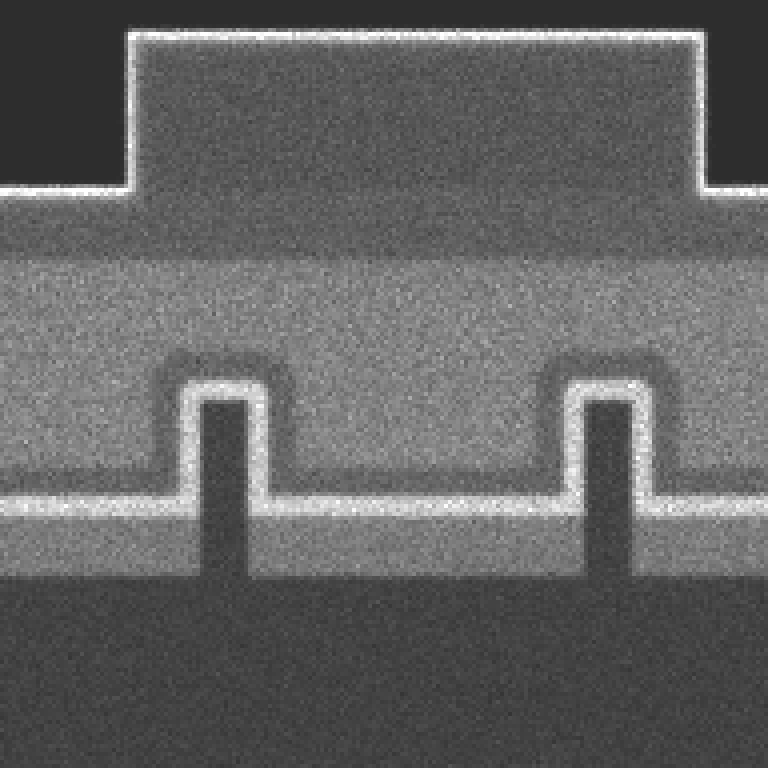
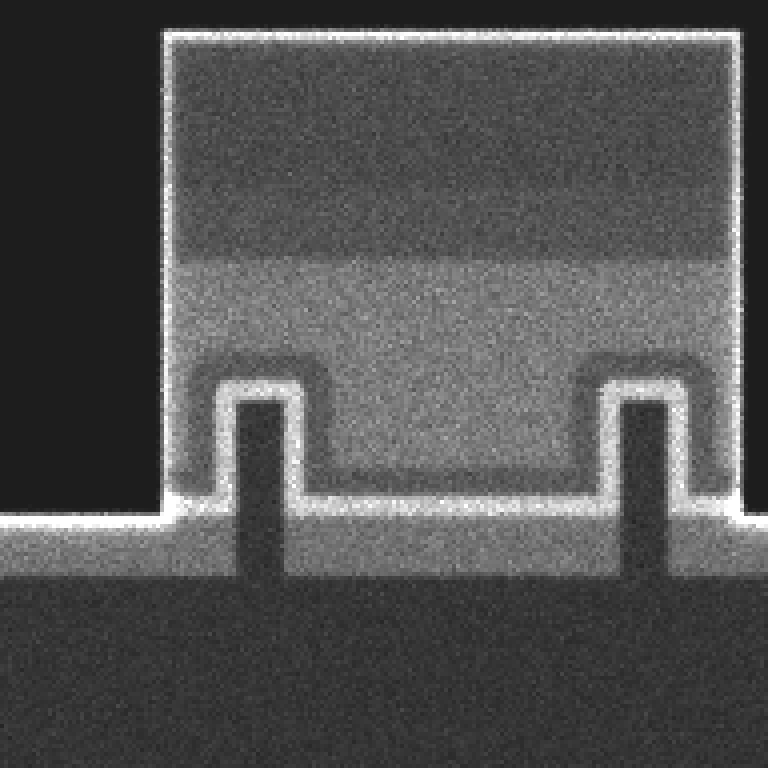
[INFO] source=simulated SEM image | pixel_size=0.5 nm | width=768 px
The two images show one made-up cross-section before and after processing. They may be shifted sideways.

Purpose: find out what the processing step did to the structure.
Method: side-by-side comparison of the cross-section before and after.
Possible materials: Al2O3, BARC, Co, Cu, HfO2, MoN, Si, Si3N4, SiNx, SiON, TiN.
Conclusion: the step removed Co and HfO2 and Si3N4 and TiN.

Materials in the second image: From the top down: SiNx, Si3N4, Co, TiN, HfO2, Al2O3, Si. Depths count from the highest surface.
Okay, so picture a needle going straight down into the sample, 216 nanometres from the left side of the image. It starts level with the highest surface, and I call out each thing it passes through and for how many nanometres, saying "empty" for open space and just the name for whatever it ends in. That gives SiNx 78, Si3N4 36, Co 104, TiN 14, HfO2 10, Al2O3 30, Si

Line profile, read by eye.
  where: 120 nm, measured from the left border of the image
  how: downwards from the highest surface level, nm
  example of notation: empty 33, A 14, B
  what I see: SiNx 78, Si3N4 36, Co 46, TiN 14, HfO2 10, Si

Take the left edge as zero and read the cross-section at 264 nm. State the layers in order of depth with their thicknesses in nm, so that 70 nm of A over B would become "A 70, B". SiNx 78, Si3N4 36, Co 104, TiN 14, HfO2 10, Al2O3 30, Si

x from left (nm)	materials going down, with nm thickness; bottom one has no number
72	empty 242, Al2O3 30, Si